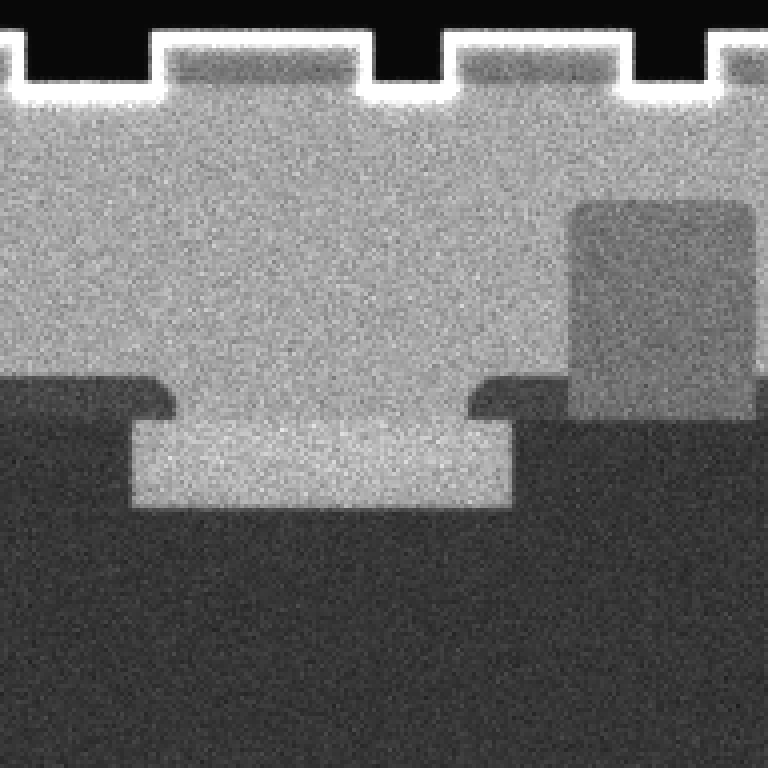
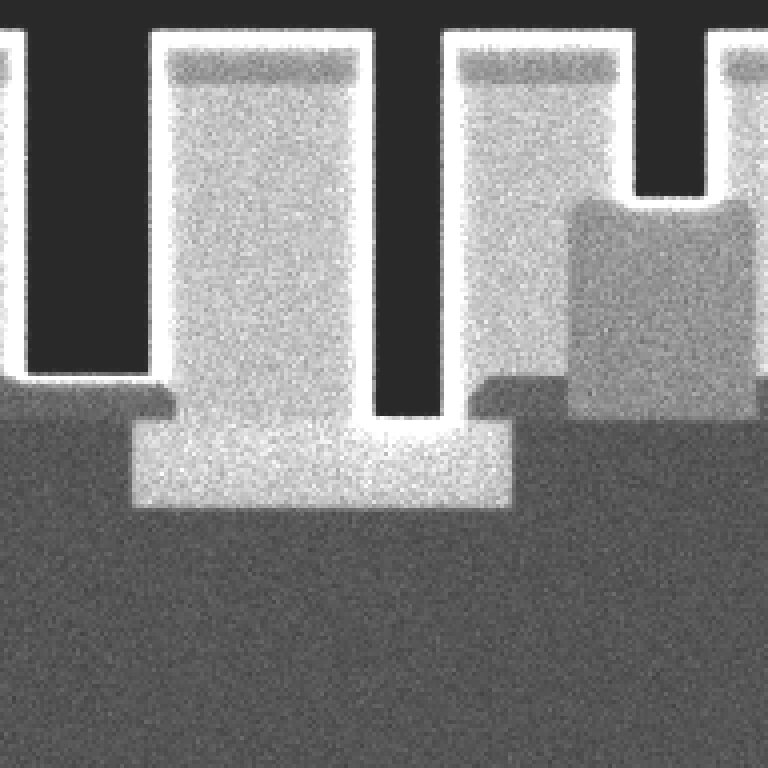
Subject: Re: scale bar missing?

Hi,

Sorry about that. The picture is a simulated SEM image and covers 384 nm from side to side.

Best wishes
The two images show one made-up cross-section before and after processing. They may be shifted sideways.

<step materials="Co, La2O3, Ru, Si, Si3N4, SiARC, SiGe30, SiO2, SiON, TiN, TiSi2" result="removed SiO2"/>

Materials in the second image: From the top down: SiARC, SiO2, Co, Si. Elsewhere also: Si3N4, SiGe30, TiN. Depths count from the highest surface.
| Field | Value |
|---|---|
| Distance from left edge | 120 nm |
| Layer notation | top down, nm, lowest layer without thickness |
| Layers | SiARC 26, SiO2 168, Co 44, Si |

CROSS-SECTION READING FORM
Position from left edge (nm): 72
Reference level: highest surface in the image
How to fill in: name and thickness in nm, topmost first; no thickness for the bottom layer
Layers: empty 172, SiGe30 22, Co 44, Si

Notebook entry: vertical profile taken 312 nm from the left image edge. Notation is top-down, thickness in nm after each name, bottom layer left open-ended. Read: SiARC 26, SiO2 58, TiN 110, Si